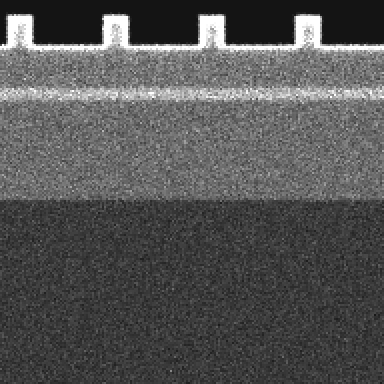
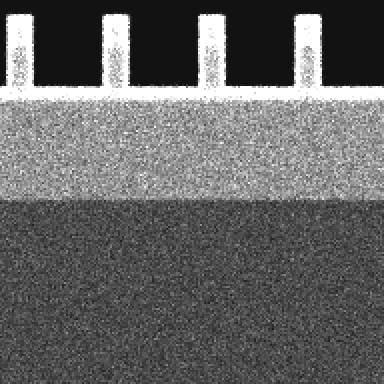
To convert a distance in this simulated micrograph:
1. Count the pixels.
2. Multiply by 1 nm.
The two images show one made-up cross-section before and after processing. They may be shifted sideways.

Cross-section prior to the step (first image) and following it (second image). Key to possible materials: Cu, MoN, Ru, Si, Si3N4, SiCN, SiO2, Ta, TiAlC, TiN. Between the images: TiN was removed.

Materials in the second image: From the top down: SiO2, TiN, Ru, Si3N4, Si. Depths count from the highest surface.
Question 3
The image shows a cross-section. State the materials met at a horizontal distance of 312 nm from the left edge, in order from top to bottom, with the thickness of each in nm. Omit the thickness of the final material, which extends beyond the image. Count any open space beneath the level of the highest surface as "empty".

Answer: SiO2 30, TiN 42, Ru 12, Si3N4 100, Si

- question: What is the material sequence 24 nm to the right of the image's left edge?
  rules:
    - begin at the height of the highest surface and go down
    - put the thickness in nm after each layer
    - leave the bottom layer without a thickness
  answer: SiO2 30, TiN 42, Ru 12, Si3N4 100, Si